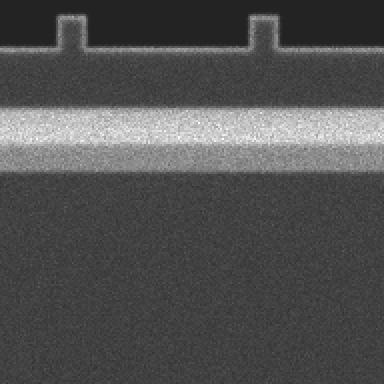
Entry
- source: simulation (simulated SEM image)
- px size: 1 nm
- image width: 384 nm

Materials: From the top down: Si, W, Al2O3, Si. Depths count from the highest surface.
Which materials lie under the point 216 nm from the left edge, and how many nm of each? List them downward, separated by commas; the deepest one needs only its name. empty 32, Si 60, W 36, Al2O3 28, Si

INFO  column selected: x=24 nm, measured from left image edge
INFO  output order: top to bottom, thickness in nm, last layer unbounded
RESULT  empty 32, Si 60, W 36, Al2O3 28, Si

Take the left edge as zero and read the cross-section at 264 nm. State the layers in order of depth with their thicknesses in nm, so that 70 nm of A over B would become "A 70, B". Si 92, W 36, Al2O3 28, Si